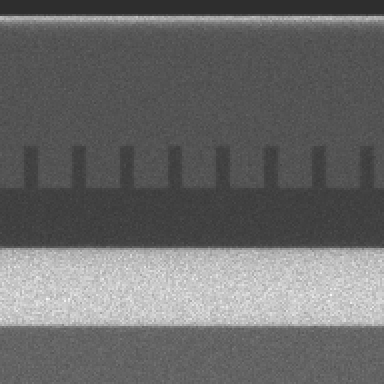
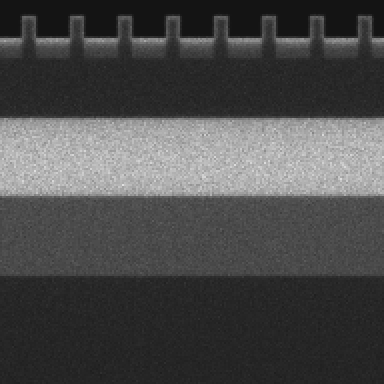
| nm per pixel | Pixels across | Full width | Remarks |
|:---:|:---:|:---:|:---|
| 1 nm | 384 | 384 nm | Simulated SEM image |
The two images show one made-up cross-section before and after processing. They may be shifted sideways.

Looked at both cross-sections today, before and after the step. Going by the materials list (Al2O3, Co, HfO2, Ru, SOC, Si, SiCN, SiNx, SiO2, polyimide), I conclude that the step removed SOC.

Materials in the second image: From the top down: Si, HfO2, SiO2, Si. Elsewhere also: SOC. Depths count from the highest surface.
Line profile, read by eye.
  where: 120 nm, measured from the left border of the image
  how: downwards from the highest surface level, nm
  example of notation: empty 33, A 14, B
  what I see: Si 102, HfO2 78, SiO2 80, Si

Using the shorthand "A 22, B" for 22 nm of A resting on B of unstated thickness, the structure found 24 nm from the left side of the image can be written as Si 102, HfO2 78, SiO2 80, Si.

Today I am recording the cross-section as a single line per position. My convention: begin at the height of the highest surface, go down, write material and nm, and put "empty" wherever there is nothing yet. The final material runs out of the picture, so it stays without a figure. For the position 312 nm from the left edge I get Si 102, HfO2 78, SiO2 80, Si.